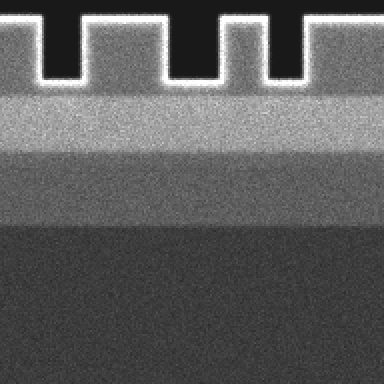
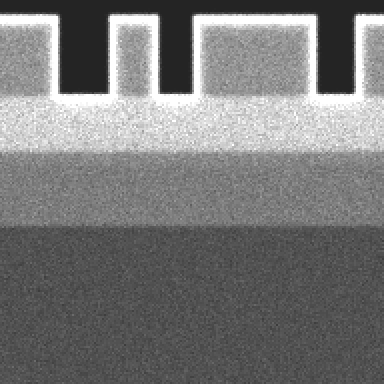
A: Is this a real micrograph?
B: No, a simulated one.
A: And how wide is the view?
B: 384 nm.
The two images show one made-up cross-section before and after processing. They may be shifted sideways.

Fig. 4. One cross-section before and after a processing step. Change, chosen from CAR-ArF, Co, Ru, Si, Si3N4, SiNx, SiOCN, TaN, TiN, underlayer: underlayer removed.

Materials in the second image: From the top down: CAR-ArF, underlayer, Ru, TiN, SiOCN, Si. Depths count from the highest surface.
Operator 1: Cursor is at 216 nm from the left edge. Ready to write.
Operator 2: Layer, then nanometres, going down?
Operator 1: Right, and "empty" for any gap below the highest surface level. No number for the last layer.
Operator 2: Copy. CAR-ArF 64, underlayer 16, Ru 56, TiN 14, SiOCN 60, Si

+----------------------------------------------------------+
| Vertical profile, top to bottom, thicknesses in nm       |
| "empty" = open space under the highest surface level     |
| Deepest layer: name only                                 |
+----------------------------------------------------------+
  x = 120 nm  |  CAR-ArF 64, underlayer 16, Ru 56, TiN 14, SiOCN 60, Si